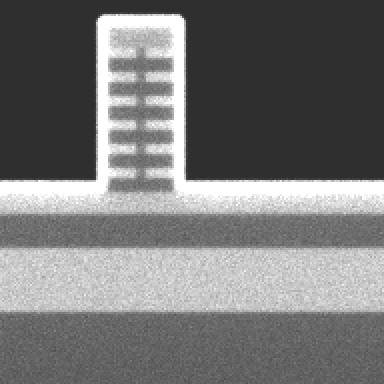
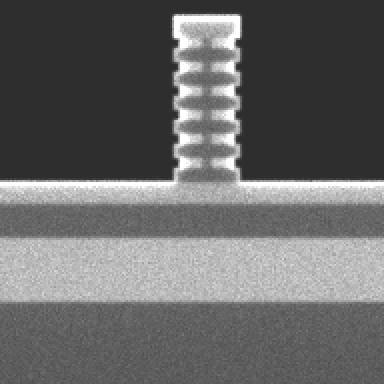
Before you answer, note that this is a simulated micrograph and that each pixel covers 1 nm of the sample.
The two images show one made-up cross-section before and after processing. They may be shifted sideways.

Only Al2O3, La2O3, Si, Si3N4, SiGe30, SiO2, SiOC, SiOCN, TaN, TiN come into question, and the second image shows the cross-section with Al2O3 removed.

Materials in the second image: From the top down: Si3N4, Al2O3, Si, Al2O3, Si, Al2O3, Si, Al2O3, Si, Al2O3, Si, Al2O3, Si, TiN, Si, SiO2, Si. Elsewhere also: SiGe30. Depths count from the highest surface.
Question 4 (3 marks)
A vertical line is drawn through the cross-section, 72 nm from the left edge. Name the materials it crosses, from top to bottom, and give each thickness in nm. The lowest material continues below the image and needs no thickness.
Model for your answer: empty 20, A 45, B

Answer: empty 166, TiN 22, Si 34, SiO2 64, Si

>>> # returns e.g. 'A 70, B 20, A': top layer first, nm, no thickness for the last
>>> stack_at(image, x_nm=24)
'empty 166, TiN 22, Si 34, SiO2 64, Si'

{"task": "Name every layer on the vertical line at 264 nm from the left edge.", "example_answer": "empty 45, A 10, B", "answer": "empty 166, TiN 22, Si 34, SiO2 64, Si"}